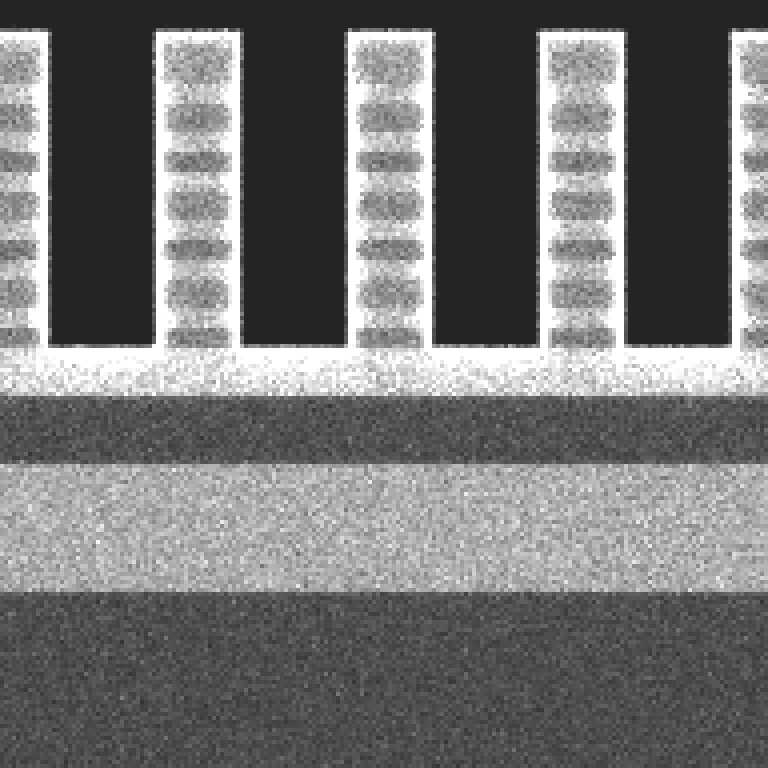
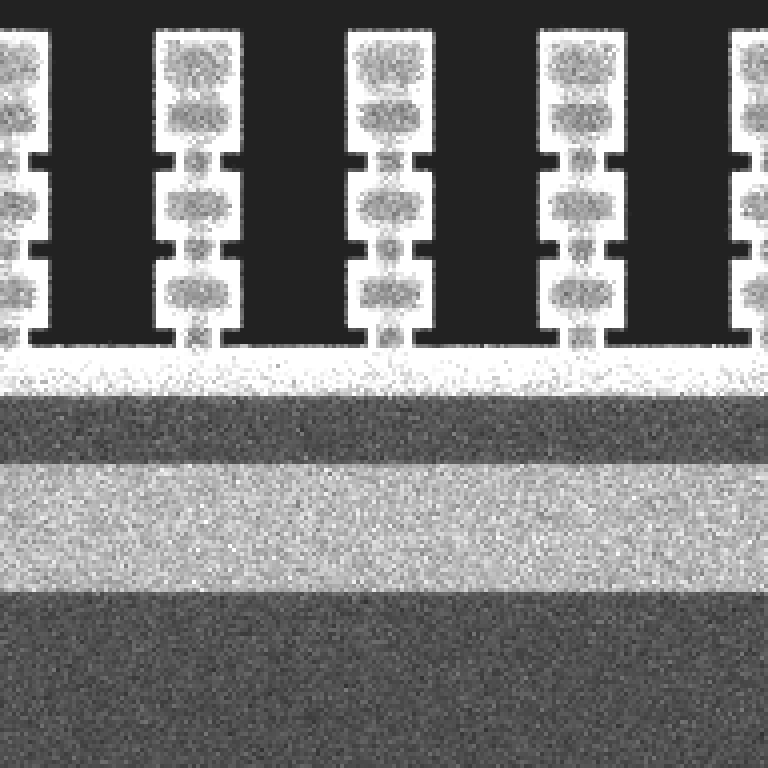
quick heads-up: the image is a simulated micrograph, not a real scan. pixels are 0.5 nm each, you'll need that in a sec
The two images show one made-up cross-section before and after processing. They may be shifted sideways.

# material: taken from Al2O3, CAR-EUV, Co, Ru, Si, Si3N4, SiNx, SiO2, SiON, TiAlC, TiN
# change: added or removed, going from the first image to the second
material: SiNx
change: removed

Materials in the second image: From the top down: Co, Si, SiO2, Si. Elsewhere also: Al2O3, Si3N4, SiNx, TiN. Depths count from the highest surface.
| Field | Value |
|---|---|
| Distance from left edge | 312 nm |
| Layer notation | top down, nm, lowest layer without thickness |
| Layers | empty 158, Co 24, Si 34, SiO2 64, Si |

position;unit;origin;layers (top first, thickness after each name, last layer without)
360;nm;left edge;empty 158, Co 24, Si 34, SiO2 64, Si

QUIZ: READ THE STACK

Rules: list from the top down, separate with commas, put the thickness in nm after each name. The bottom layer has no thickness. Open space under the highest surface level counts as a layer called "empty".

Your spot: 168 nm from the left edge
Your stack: empty 158, Co 24, Si 34, SiO2 64, Si